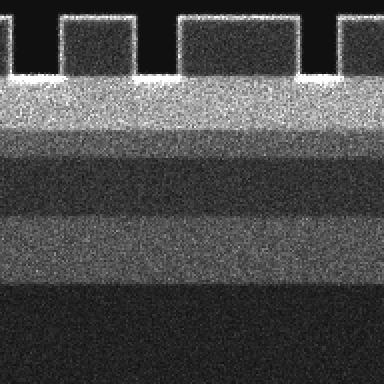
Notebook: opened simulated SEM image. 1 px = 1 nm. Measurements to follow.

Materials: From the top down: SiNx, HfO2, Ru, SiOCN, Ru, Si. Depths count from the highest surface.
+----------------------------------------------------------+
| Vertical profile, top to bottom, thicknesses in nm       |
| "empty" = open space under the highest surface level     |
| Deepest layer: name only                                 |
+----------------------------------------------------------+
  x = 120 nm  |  SiNx 60, HfO2 54, Ru 28, SiOCN 58, Ru 68, Si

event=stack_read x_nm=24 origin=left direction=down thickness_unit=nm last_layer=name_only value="empty 60, HfO2 54, Ru 28, SiOCN 58, Ru 68, Si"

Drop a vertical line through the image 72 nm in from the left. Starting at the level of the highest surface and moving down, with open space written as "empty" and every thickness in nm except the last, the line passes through SiNx 60, HfO2 54, Ru 28, SiOCN 58, Ru 68, Si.